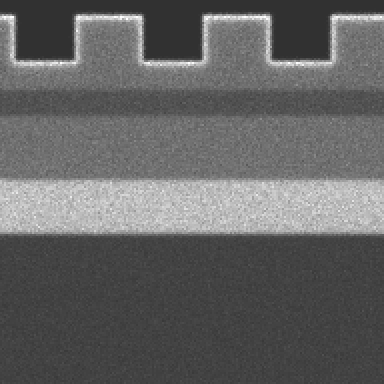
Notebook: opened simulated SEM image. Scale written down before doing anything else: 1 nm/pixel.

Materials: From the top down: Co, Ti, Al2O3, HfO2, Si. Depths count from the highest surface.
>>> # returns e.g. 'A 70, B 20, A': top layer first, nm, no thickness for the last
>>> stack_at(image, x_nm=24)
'empty 46, Co 28, Ti 26, Al2O3 64, HfO2 54, Si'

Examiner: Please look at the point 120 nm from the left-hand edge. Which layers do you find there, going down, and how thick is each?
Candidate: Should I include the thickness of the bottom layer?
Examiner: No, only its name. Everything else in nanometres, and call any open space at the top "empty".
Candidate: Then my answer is Co 74, Ti 26, Al2O3 64, HfO2 54, Si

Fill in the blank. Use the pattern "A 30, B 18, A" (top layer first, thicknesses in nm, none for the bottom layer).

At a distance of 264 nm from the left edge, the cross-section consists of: Co 74, Ti 26, Al2O3 64, HfO2 54, Si